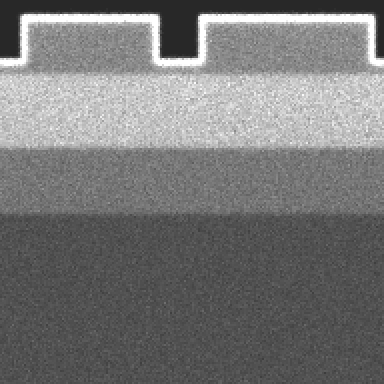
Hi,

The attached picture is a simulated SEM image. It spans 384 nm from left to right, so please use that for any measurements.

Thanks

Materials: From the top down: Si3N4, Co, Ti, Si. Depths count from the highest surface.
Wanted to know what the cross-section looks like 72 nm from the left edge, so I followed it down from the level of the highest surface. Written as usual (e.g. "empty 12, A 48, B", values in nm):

Si3N4 58, Co 74, Ti 66, Si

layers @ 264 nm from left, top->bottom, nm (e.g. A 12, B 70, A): Si3N4 58, Co 74, Ti 66, Si